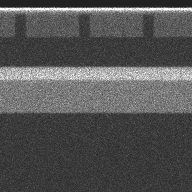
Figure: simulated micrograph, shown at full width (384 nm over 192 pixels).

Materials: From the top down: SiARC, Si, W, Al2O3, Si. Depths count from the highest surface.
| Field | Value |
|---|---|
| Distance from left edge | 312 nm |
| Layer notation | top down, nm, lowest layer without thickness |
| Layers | SiARC 58, Si 60, W 26, Al2O3 66, Si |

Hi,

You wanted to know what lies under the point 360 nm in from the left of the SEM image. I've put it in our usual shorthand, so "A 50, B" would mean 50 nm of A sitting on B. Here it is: SiARC 58, Si 60, W 26, Al2O3 66, Si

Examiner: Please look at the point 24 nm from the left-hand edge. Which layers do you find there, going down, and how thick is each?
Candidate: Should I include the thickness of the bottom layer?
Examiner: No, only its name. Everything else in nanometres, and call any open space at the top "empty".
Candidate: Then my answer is SiARC 58, Si 60, W 26, Al2O3 66, Si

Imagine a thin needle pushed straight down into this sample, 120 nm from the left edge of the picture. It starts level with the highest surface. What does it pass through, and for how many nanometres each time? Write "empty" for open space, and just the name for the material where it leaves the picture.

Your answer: SiARC 58, Si 60, W 26, Al2O3 66, Si